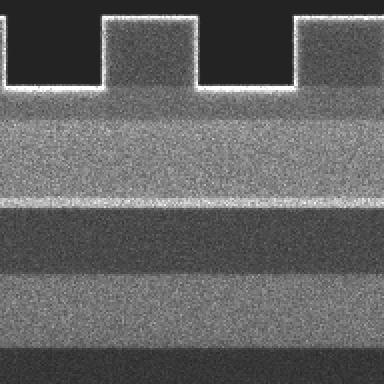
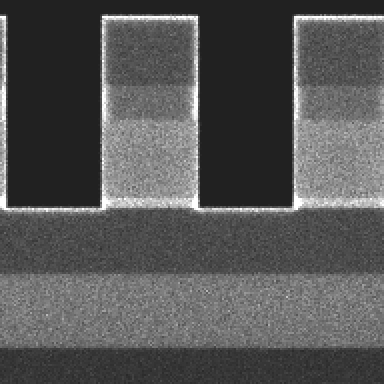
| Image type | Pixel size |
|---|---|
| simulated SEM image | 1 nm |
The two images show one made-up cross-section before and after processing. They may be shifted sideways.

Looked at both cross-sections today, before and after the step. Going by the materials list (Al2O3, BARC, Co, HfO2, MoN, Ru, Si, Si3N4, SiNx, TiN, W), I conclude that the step removed Al2O3 and HfO2 and Ru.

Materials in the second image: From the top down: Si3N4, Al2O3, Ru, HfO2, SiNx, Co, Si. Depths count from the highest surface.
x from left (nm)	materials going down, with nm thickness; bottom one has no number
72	empty 192, SiNx 66, Co 74, Si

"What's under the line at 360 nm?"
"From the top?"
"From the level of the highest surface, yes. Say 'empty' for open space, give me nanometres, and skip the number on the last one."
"Si3N4 70, Al2O3 34, Ru 78, HfO2 10, SiNx 66, Co 74, Si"